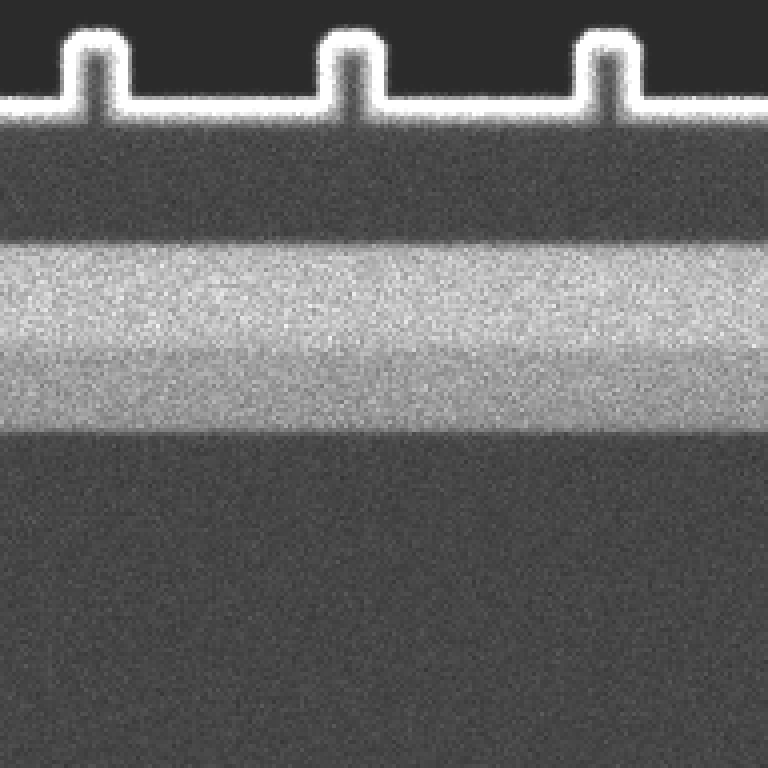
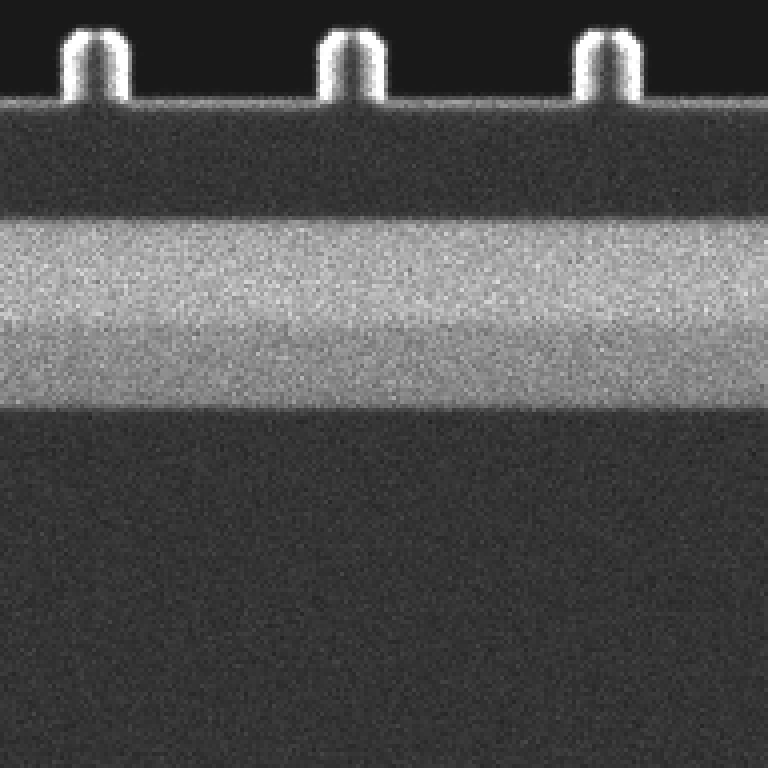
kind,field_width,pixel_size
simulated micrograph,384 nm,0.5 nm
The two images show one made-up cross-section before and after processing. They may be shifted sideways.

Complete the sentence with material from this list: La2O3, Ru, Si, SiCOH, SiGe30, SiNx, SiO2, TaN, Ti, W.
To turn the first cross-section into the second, SiO2 must be removed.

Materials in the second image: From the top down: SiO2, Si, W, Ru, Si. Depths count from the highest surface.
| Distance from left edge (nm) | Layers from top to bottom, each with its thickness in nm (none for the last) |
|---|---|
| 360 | empty 34, Si 60, W 52, Ru 42, Si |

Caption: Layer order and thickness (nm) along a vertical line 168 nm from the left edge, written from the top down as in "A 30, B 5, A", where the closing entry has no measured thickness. SiO2 34, Si 60, W 52, Ru 42, Si